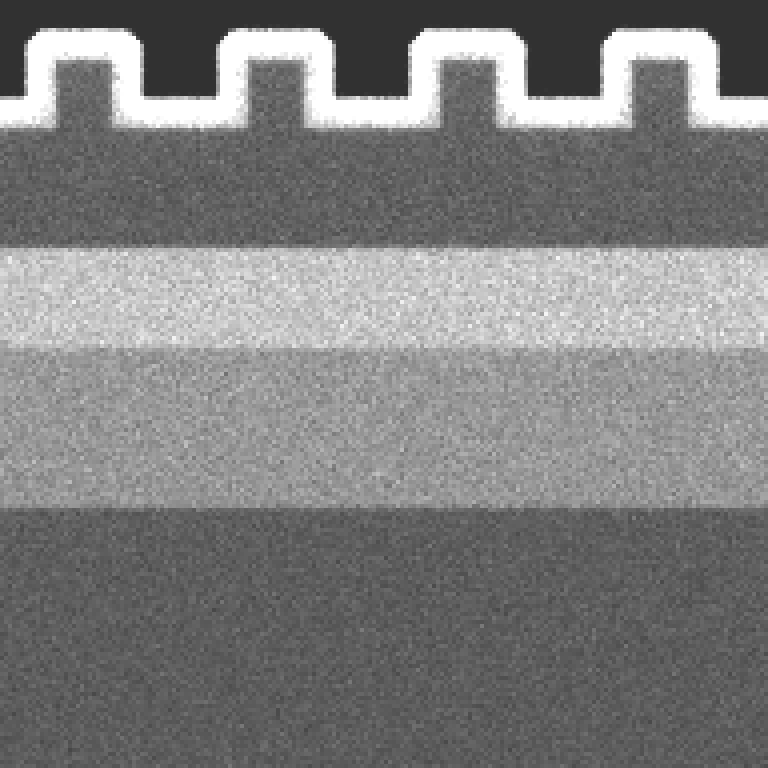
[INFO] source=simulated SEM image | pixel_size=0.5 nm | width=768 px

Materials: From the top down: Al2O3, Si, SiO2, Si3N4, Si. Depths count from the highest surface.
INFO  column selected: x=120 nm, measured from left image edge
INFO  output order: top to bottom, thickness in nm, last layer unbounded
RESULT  Al2O3 48, Si 60, SiO2 50, Si3N4 80, Si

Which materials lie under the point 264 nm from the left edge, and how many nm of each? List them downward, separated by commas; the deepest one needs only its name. empty 34, Al2O3 14, Si 60, SiO2 50, Si3N4 80, Si